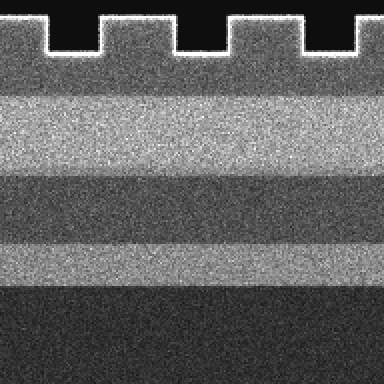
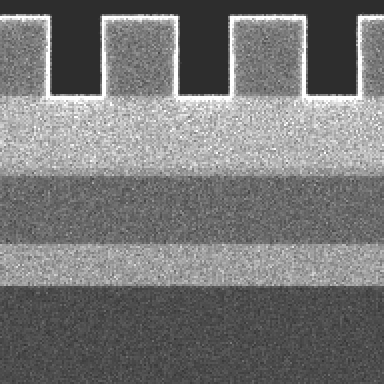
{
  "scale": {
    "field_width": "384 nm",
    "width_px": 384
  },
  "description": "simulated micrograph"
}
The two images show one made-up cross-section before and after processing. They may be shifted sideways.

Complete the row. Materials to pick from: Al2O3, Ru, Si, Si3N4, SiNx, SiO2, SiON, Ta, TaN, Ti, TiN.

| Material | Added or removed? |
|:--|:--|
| Si3N4 | removed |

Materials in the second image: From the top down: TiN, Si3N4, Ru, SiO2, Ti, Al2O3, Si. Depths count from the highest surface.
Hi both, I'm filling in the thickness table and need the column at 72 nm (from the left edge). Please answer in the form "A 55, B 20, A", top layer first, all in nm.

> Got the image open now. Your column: empty 80, Ru 72, SiO2 8, Ti 68, Al2O3 42, Si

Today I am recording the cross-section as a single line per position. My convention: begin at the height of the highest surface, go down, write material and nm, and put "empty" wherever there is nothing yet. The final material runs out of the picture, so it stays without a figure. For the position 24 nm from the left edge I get TiN 36, Si3N4 44, Ru 72, SiO2 8, Ti 68, Al2O3 42, Si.